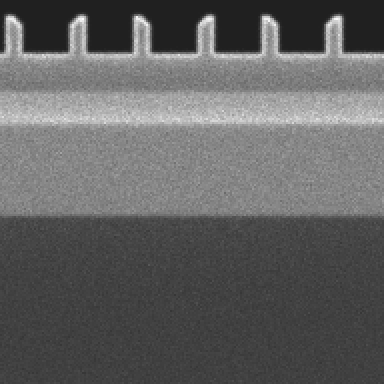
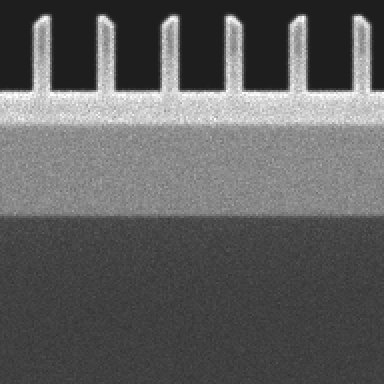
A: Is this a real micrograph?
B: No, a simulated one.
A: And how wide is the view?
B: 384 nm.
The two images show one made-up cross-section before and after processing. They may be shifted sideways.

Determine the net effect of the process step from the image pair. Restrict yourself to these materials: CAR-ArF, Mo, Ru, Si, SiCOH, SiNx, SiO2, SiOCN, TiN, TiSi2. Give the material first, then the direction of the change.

TiN: removed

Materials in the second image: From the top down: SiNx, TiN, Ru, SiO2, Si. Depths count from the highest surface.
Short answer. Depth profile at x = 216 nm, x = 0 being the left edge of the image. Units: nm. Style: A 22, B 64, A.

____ empty 76, Ru 32, SiO2 92, Si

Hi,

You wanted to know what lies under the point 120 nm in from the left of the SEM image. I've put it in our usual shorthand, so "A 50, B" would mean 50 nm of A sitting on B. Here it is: empty 76, Ru 32, SiO2 92, Si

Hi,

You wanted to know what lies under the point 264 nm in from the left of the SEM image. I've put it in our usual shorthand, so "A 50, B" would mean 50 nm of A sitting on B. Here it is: empty 76, Ru 32, SiO2 92, Si